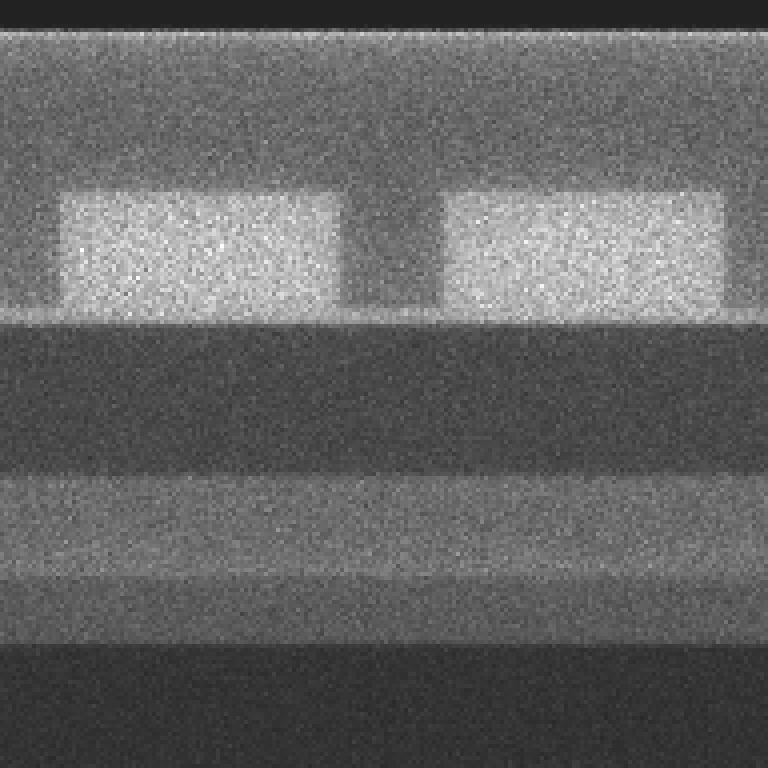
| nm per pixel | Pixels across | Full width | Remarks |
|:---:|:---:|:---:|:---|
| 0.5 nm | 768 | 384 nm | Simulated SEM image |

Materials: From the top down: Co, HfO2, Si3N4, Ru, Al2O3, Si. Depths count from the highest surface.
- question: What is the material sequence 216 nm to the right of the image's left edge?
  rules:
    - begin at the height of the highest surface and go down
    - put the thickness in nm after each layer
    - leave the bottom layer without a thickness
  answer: Co 138, HfO2 8, Si3N4 76, Ru 50, Al2O3 34, Si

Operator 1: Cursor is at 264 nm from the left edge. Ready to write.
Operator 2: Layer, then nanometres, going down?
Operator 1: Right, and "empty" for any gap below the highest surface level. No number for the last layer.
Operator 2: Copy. Co 80, HfO2 66, Si3N4 76, Ru 50, Al2O3 34, Si